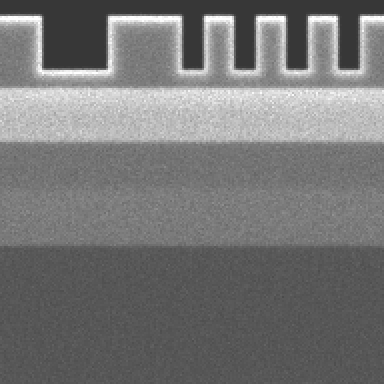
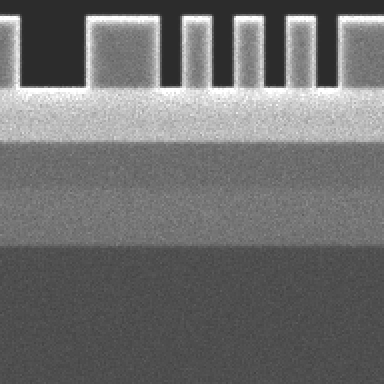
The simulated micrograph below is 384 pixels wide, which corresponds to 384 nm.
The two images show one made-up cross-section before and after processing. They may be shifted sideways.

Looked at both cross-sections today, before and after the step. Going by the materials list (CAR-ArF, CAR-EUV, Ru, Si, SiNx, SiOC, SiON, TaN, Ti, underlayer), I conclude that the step removed underlayer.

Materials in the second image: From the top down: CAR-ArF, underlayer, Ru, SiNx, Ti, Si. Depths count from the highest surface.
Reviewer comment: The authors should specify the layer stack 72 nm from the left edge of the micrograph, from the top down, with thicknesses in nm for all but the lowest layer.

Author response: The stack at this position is empty 72, Ru 54, SiNx 46, Ti 58, Si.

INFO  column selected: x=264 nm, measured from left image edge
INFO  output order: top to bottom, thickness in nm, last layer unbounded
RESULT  empty 72, Ru 54, SiNx 46, Ti 58, Si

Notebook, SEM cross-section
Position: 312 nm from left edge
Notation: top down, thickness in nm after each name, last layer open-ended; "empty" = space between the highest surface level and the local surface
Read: CAR-ArF 54, underlayer 18, Ru 54, SiNx 46, Ti 58, Si